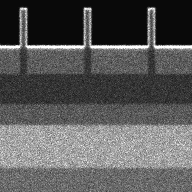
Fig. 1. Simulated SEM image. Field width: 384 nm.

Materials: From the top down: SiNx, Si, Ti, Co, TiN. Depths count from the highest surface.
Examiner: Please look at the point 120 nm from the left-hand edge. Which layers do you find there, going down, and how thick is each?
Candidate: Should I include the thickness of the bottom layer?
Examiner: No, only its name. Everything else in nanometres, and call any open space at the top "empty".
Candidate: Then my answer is empty 76, SiNx 56, Si 60, Ti 42, Co 86, TiN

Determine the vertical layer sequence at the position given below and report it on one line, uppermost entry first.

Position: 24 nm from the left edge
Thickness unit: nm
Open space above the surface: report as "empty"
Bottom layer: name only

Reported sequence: empty 76, SiNx 56, Si 60, Ti 42, Co 86, TiN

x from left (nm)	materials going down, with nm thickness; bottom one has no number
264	empty 76, SiNx 56, Si 60, Ti 42, Co 86, TiN